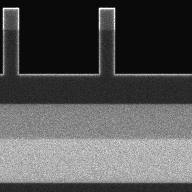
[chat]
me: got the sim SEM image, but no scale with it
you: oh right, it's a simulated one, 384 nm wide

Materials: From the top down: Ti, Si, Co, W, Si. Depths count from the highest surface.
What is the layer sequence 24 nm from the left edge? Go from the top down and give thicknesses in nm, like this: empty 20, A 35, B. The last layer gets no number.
Ti 44, Si 148, Co 70, W 88, Si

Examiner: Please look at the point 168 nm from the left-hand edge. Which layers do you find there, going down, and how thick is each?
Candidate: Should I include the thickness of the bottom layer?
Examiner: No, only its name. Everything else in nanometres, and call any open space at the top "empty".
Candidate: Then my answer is empty 132, Si 60, Co 70, W 88, Si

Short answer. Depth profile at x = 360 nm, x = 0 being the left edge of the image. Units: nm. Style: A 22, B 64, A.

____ empty 132, Si 60, Co 70, W 88, Si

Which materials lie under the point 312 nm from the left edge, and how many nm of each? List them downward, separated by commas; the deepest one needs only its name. empty 132, Si 60, Co 70, W 88, Si